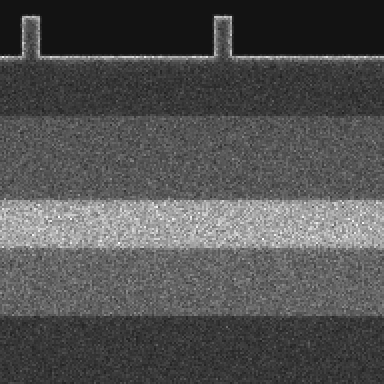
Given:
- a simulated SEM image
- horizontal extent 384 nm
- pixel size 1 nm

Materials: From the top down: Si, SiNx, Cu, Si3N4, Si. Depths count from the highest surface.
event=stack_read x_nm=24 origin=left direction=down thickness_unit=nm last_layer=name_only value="Si 100, SiNx 84, Cu 48, Si3N4 68, Si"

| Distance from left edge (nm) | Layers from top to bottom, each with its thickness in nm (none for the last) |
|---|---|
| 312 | empty 40, Si 60, SiNx 84, Cu 48, Si3N4 68, Si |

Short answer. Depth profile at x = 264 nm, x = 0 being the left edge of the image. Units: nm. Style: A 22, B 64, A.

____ empty 40, Si 60, SiNx 84, Cu 48, Si3N4 68, Si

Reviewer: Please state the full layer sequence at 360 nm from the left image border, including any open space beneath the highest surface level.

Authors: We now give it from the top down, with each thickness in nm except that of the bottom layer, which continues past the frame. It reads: empty 40, Si 60, SiNx 84, Cu 48, Si3N4 68, Si